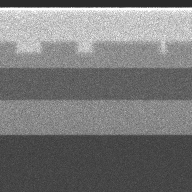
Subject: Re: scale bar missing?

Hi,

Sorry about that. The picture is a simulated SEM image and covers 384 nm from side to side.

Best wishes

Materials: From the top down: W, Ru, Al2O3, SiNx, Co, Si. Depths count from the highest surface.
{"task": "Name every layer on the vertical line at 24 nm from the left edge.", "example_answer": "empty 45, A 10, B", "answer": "W 66, Ru 6, Al2O3 48, SiNx 64, Co 70, Si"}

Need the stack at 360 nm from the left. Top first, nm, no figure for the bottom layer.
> W 66, Ru 6, Al2O3 48, SiNx 64, Co 70, Si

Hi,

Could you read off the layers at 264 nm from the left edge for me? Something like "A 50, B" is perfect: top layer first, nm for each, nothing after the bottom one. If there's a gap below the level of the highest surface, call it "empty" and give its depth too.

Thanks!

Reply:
W 66, Ru 6, Al2O3 48, SiNx 64, Co 70, Si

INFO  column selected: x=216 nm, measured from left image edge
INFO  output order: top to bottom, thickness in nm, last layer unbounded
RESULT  W 66, Ru 6, Al2O3 48, SiNx 64, Co 70, Si